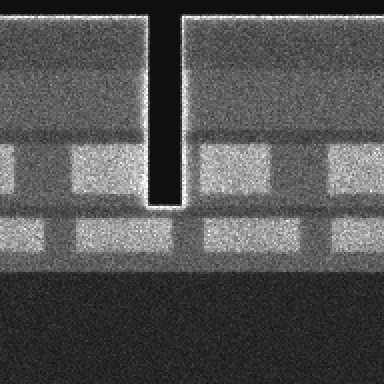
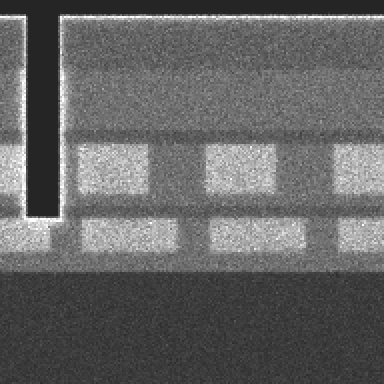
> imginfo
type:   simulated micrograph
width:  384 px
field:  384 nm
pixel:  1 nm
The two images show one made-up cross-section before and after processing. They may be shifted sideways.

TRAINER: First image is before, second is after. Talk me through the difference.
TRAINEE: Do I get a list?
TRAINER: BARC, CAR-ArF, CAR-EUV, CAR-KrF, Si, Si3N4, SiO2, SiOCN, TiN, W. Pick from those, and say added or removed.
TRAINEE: removed: Si3N4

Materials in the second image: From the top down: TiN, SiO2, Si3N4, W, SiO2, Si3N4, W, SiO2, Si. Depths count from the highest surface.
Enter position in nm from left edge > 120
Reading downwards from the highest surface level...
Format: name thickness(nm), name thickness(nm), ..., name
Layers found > TiN 54, SiO2 60, Si3N4 14, W 50, SiO2 12, Si3N4 12, W 34, SiO2 20, Si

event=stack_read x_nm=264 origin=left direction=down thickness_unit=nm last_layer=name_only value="TiN 54, SiO2 60, Si3N4 14, W 50, SiO2 12, Si3N4 12, W 34, SiO2 20, Si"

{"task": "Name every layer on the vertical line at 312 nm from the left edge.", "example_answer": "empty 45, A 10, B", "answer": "TiN 54, SiO2 60, Si3N4 14, SiO2 62, Si3N4 12, SiO2 54, Si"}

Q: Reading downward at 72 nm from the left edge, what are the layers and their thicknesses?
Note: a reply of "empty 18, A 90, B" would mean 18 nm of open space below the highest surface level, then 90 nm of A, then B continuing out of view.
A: TiN 54, SiO2 60, Si3N4 14, SiO2 62, Si3N4 12, SiO2 54, Si